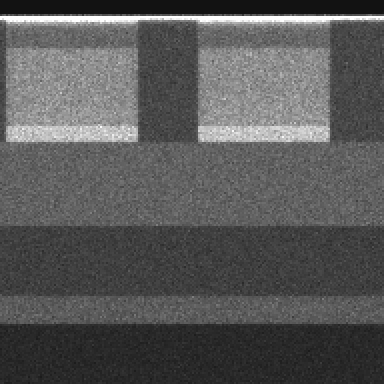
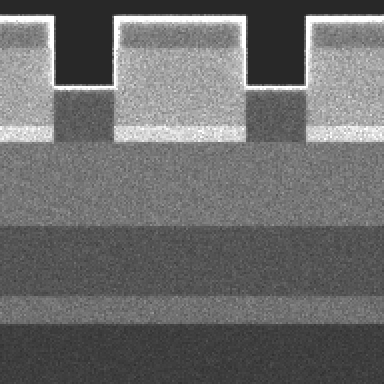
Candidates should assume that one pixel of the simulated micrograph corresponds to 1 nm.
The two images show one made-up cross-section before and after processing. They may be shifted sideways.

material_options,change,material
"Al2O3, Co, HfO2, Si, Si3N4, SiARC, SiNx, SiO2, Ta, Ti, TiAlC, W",removed,Si3N4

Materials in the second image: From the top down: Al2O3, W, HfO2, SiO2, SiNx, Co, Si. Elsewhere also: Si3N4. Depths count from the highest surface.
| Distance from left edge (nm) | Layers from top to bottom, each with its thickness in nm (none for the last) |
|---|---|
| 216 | Al2O3 32, W 78, HfO2 16, SiO2 84, SiNx 70, Co 28, Si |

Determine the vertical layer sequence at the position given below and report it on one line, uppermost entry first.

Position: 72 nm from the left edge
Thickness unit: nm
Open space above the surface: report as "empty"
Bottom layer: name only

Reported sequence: empty 70, Si3N4 56, SiO2 84, SiNx 70, Co 28, Si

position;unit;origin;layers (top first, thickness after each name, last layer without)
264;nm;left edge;empty 70, Si3N4 56, SiO2 84, SiNx 70, Co 28, Si